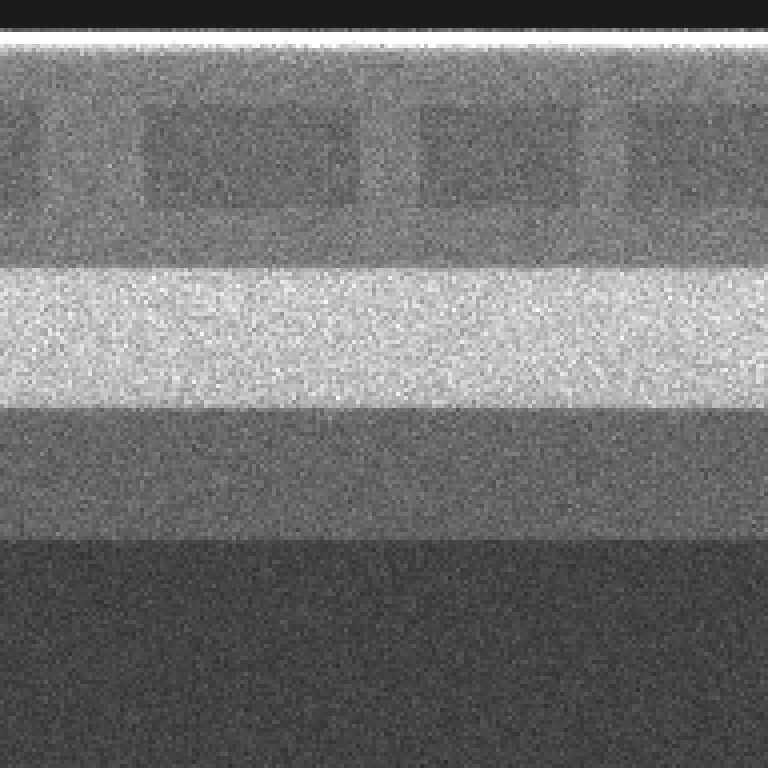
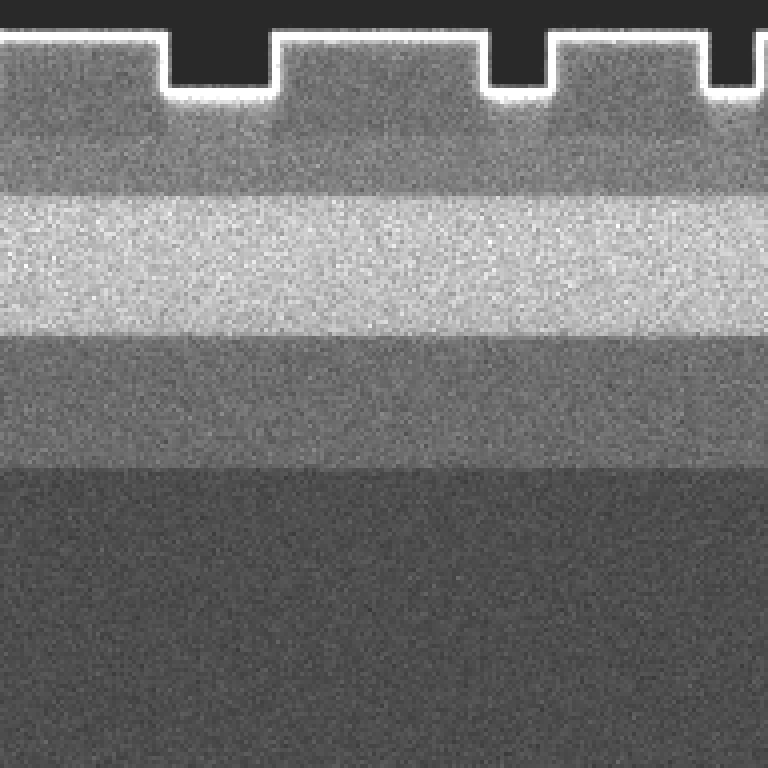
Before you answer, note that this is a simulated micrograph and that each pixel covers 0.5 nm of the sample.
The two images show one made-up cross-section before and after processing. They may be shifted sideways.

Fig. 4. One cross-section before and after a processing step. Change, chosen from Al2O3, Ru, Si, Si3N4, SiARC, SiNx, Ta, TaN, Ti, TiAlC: SiARC removed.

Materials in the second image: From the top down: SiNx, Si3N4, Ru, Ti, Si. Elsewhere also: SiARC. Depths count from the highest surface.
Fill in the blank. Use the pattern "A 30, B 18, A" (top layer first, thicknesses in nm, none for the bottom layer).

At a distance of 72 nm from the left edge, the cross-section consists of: SiNx 52, Si3N4 30, Ru 70, Ti 66, Si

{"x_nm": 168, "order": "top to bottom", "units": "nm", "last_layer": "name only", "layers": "SiNx 52, Si3N4 30, Ru 70, Ti 66, Si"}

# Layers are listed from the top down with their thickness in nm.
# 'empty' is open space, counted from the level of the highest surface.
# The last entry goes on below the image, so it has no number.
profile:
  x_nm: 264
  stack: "empty 28, SiARC 46, Si3N4 8, Ru 70, Ti 66, Si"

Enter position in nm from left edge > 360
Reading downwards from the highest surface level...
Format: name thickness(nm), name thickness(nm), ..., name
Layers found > empty 28, SiARC 46, Si3N4 8, Ru 70, Ti 66, Si